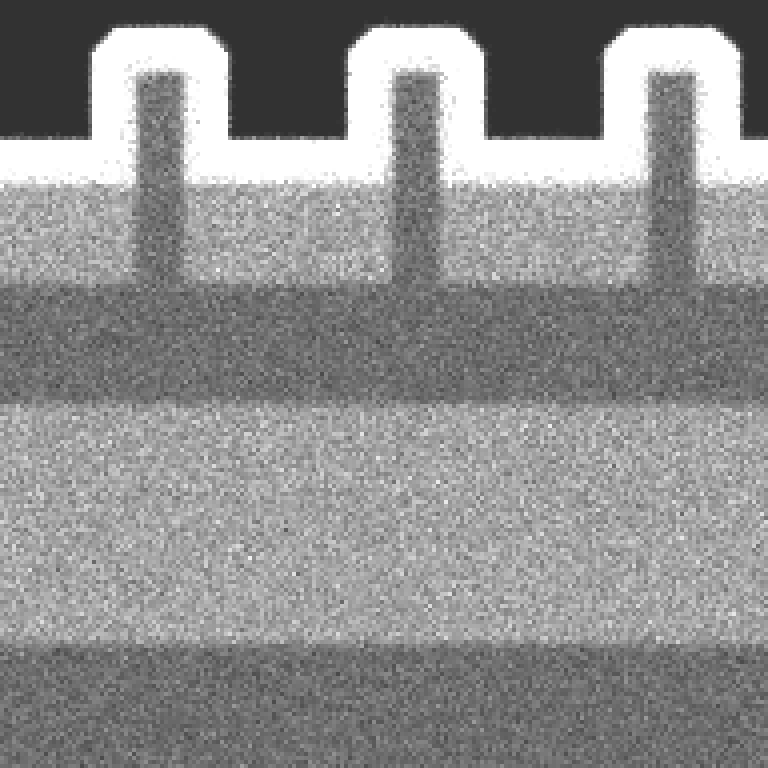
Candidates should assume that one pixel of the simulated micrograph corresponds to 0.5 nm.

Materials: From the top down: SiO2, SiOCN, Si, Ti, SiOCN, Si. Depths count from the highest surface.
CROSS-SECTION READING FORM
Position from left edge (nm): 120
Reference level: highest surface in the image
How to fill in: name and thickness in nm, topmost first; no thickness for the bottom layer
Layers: empty 56, SiO2 20, SiOCN 50, Si 60, Ti 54, SiOCN 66, Si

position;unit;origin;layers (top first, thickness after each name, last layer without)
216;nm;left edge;SiO2 20, Si 166, Ti 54, SiOCN 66, Si